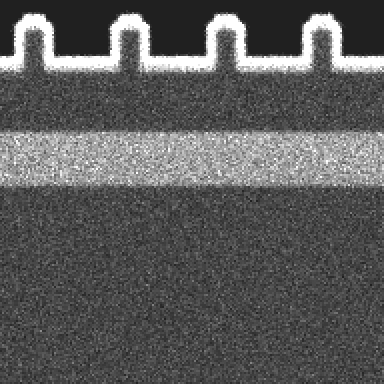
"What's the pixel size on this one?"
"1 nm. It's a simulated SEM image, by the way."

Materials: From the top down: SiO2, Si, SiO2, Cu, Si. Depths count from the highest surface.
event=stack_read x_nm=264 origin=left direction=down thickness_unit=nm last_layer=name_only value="empty 42, SiO2 14, Si 60, SiO2 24, Cu 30, Si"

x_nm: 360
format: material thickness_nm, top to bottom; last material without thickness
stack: empty 42, SiO2 14, Si 60, SiO2 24, Cu 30, Si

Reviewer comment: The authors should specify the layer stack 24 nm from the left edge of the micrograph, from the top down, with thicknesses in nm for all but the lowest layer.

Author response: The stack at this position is SiO2 14, Si 102, SiO2 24, Cu 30, Si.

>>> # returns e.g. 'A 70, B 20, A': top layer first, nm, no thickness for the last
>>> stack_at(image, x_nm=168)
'empty 42, SiO2 14, Si 60, SiO2 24, Cu 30, Si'